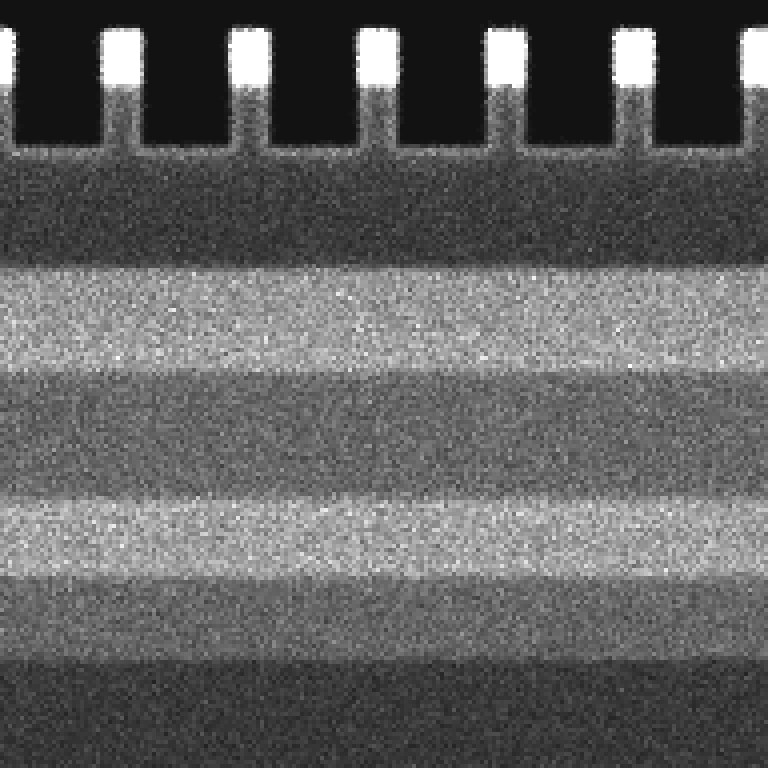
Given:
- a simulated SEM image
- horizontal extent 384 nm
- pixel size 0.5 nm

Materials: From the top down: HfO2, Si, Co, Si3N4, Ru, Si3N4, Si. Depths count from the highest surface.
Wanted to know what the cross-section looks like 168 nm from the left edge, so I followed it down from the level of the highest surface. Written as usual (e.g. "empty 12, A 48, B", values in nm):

empty 58, Si 60, Co 52, Si3N4 64, Ru 38, Si3N4 42, Si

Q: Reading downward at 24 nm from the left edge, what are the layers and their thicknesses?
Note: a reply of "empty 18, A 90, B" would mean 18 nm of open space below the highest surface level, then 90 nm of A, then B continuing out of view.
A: empty 58, Si 60, Co 52, Si3N4 64, Ru 38, Si3N4 42, Si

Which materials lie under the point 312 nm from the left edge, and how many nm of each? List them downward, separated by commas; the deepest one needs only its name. HfO2 26, Si 92, Co 52, Si3N4 64, Ru 38, Si3N4 42, Si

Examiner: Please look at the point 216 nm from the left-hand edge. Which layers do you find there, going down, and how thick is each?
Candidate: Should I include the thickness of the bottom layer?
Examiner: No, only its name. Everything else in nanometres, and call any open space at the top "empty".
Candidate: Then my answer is empty 58, Si 60, Co 52, Si3N4 64, Ru 38, Si3N4 42, Si